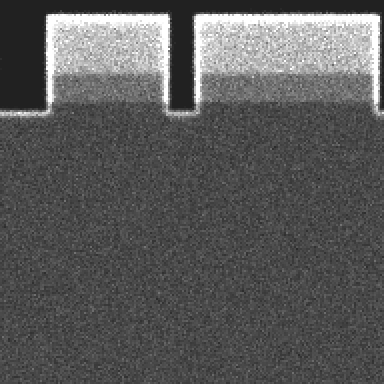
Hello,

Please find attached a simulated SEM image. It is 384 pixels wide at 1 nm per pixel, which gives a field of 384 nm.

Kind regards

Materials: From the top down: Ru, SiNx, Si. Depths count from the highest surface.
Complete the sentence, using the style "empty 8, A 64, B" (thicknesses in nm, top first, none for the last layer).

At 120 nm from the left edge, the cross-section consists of Ru 58, SiNx 28, Si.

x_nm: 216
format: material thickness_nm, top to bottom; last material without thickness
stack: Ru 58, SiNx 28, Si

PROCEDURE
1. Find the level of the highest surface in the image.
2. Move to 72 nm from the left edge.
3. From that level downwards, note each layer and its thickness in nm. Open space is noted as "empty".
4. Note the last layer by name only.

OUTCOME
Ru 58, SiNx 28, Si